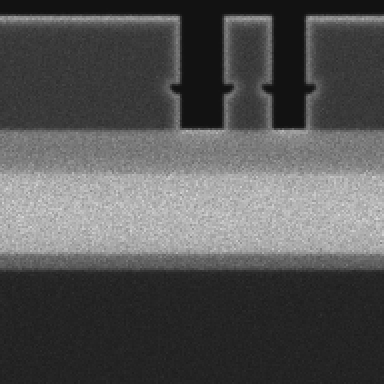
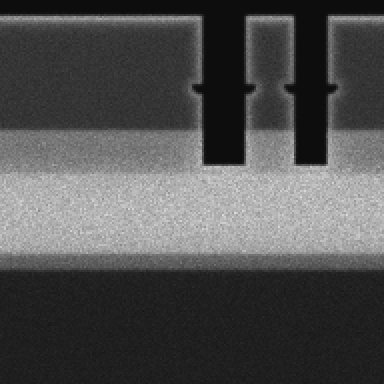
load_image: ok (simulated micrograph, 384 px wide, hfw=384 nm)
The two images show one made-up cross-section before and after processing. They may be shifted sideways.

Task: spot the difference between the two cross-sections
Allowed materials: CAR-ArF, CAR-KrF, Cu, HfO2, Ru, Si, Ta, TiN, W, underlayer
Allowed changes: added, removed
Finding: removed W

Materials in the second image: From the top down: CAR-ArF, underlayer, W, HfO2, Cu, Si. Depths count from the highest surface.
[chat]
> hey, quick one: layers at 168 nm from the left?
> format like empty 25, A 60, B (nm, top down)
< CAR-ArF 68, underlayer 46, W 44, HfO2 80, Cu 16, Si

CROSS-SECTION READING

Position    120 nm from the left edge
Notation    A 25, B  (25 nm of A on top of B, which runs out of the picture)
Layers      CAR-ArF 68, underlayer 46, W 44, HfO2 80, Cu 16, Si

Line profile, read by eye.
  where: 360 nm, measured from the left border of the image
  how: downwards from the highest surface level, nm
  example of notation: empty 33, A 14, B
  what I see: CAR-ArF 68, underlayer 46, W 44, HfO2 80, Cu 16, Si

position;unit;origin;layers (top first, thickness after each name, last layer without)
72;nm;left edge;CAR-ArF 68, underlayer 46, W 44, HfO2 80, Cu 16, Si